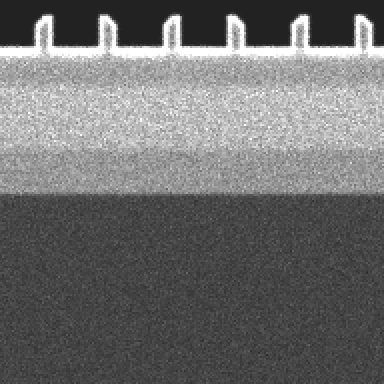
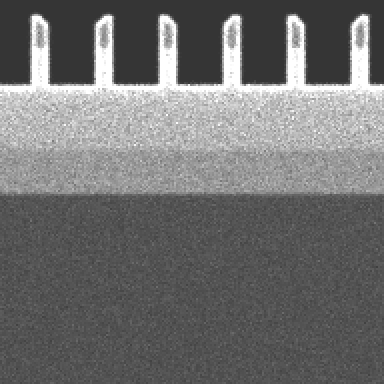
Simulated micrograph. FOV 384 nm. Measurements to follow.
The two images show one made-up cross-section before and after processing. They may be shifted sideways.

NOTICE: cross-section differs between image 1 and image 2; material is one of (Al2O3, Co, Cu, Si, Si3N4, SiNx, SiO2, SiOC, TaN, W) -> removed: Al2O3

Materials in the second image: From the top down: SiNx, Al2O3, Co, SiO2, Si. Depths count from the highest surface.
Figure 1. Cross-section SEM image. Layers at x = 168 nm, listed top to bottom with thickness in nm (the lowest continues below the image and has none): empty 2, SiNx 30, Al2O3 38, Co 64, SiO2 44, Si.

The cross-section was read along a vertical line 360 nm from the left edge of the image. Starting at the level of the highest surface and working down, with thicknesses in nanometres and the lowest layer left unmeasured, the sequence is SiNx 32, Al2O3 38, Co 64, SiO2 44, Si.